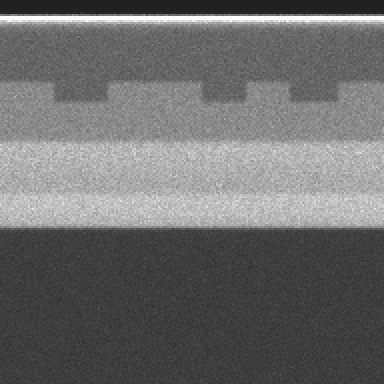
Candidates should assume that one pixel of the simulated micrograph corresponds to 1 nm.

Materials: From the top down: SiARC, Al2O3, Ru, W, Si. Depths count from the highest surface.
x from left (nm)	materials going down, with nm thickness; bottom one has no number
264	SiARC 66, Al2O3 60, Ru 52, W 34, Si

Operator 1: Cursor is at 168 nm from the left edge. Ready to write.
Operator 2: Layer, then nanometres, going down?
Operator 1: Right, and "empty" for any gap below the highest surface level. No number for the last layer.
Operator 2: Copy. SiARC 66, Al2O3 60, Ru 52, W 34, Si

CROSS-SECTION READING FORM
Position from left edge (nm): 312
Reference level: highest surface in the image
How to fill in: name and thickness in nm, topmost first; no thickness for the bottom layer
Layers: SiARC 86, Al2O3 40, Ru 52, W 34, Si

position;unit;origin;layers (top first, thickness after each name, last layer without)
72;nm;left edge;SiARC 86, Al2O3 40, Ru 52, W 34, Si